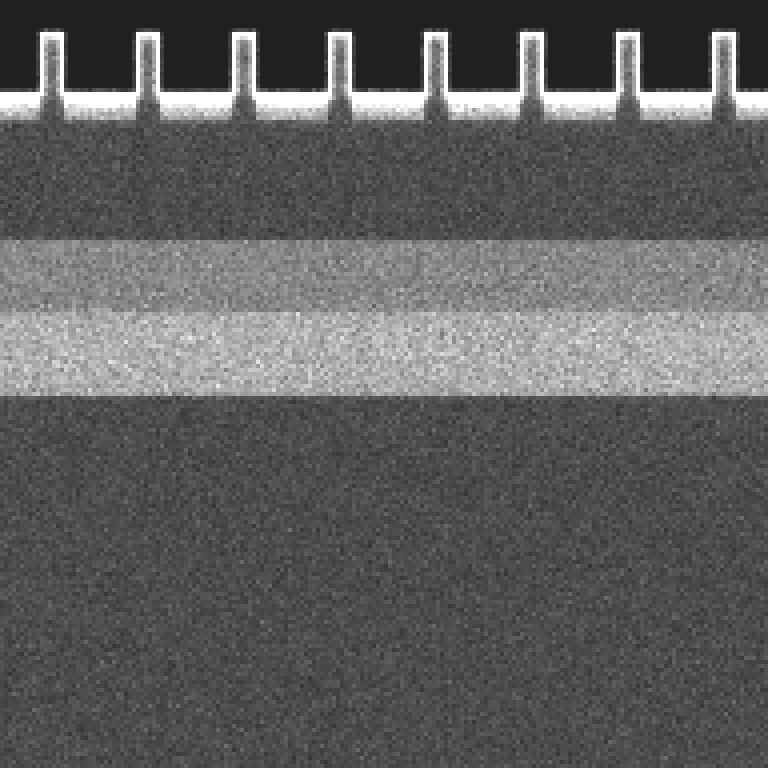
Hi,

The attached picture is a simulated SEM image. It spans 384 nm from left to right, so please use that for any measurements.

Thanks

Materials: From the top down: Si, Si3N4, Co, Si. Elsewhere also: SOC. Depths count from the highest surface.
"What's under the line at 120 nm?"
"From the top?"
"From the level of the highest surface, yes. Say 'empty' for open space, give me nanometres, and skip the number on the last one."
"Si 104, Si3N4 36, Co 42, Si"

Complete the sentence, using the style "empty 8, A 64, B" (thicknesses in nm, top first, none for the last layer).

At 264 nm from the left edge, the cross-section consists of Si 104, Si3N4 36, Co 42, Si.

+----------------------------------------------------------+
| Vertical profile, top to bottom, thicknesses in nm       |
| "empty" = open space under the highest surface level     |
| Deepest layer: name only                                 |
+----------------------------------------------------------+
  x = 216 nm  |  Si 104, Si3N4 36, Co 42, Si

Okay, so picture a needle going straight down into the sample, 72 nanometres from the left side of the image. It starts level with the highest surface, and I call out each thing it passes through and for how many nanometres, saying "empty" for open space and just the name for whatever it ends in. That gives Si 104, Si3N4 36, Co 42, Si